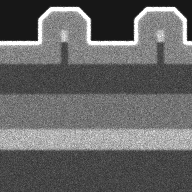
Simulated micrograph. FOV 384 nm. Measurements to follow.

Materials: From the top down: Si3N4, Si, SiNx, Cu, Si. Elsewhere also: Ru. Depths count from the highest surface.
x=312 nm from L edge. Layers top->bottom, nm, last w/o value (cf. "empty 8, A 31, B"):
Si3N4 112, Si 60, SiNx 70, Cu 42, Si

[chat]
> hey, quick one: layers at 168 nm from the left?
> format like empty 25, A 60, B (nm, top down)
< empty 12, Si3N4 100, Si 60, SiNx 70, Cu 42, Si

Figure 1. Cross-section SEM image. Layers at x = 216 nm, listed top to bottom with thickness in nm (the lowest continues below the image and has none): empty 68, Si3N4 44, Si 60, SiNx 70, Cu 42, Si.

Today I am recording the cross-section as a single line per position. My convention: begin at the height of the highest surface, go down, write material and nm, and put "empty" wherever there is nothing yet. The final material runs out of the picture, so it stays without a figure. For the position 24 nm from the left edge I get empty 68, Si3N4 44, Si 60, SiNx 70, Cu 42, Si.